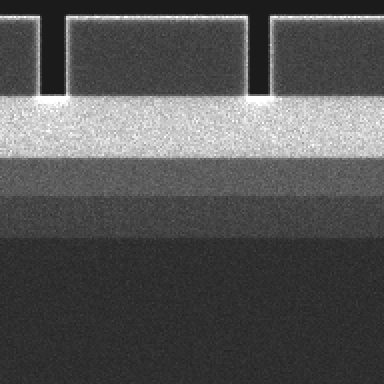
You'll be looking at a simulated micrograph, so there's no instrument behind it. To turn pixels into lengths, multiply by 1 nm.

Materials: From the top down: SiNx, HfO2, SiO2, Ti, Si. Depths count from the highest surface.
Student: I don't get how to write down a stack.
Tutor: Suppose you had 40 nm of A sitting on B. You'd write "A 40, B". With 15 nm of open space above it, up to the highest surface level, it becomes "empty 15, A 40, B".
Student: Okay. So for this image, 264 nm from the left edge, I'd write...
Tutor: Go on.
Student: empty 80, HfO2 62, SiO2 38, Ti 42, Si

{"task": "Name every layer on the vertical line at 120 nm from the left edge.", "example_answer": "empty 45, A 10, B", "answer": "SiNx 80, HfO2 62, SiO2 38, Ti 42, Si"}